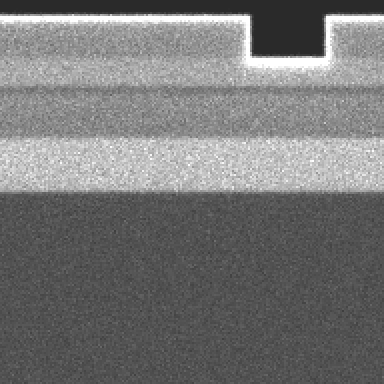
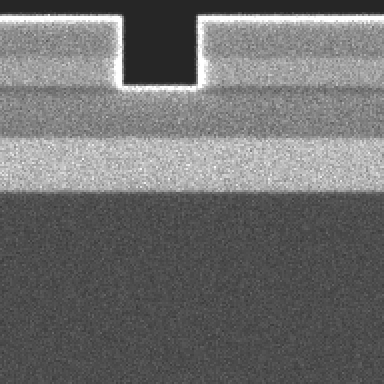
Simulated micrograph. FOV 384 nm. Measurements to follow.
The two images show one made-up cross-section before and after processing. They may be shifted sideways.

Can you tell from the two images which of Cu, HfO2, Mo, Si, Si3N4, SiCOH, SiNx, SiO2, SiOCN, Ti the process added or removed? Yes, it removed SiO2.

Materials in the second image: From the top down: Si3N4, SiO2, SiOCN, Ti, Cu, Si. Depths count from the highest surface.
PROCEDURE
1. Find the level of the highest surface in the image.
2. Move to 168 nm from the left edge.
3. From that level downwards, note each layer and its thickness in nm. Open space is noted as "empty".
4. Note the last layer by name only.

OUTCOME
empty 70, SiOCN 8, Ti 44, Cu 54, Si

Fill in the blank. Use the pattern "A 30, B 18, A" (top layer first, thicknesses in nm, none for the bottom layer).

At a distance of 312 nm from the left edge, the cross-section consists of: Si3N4 42, SiO2 28, SiOCN 8, Ti 44, Cu 54, Si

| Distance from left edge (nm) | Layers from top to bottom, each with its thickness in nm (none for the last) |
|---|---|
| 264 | Si3N4 42, SiO2 28, SiOCN 8, Ti 44, Cu 54, Si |